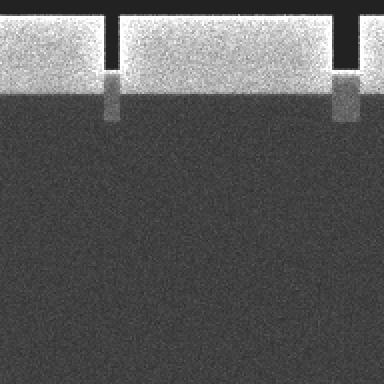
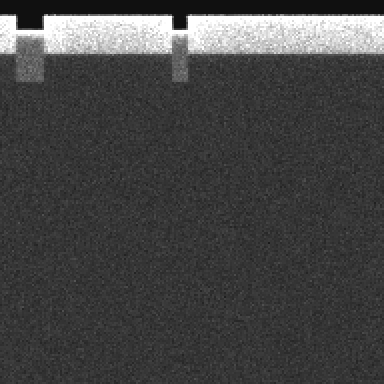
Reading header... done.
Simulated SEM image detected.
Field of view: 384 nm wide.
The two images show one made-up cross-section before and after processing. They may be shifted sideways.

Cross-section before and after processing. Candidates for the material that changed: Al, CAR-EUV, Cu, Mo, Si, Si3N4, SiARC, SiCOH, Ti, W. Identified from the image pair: W (removed).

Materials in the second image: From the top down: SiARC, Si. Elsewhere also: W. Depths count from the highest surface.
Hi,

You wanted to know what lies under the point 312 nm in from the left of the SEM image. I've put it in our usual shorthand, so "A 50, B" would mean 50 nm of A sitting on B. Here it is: W 38, Si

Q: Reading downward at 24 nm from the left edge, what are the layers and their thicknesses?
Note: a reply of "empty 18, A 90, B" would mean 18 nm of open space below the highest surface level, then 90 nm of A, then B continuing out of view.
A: empty 14, SiARC 52, Si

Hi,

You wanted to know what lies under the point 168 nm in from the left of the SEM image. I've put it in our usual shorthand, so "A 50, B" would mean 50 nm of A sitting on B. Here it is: W 38, Si